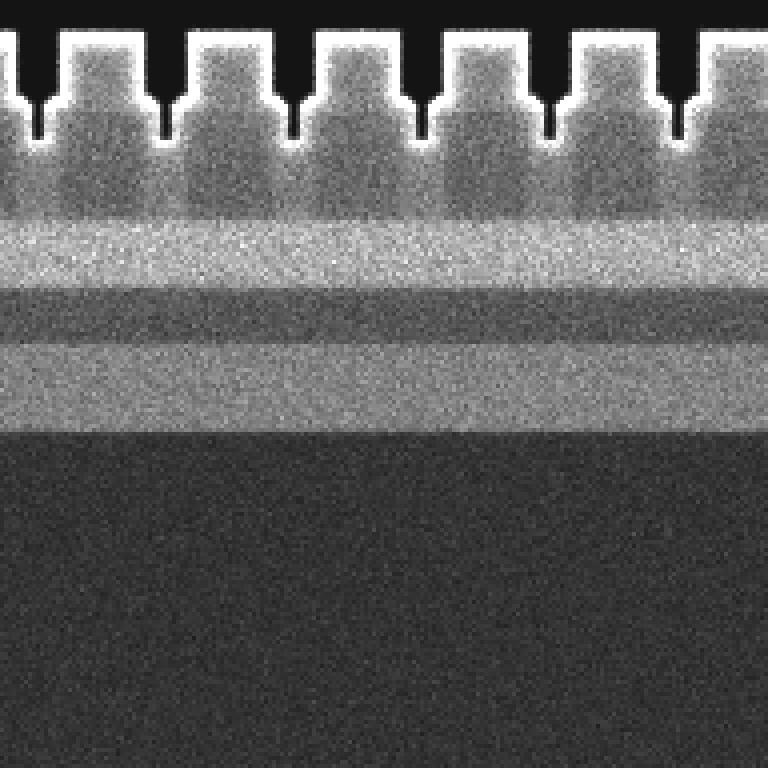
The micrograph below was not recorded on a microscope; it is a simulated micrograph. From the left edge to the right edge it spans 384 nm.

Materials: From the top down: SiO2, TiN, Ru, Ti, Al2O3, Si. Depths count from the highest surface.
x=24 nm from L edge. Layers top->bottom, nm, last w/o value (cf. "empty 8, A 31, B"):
empty 34, SiO2 60, Ru 34, Ti 28, Al2O3 44, Si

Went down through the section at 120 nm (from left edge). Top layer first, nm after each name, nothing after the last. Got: SiO2 40, TiN 54, Ru 34, Ti 28, Al2O3 44, Si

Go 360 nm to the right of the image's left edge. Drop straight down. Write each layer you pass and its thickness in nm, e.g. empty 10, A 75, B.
SiO2 40, TiN 54, Ru 34, Ti 28, Al2O3 44, Si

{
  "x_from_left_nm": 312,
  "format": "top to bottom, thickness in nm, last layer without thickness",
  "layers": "SiO2 40, TiN 54, Ru 34, Ti 28, Al2O3 44, Si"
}